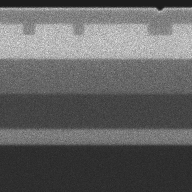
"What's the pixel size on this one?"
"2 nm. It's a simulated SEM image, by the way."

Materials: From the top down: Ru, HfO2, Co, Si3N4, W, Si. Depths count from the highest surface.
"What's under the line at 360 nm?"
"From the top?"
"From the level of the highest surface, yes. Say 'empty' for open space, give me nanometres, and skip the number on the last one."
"Ru 32, HfO2 70, Co 70, Si3N4 70, W 32, Si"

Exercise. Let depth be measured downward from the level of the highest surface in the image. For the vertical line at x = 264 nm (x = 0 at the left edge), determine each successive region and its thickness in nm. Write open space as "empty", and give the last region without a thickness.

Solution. Ru 32, HfO2 70, Co 70, Si3N4 70, W 32, Si